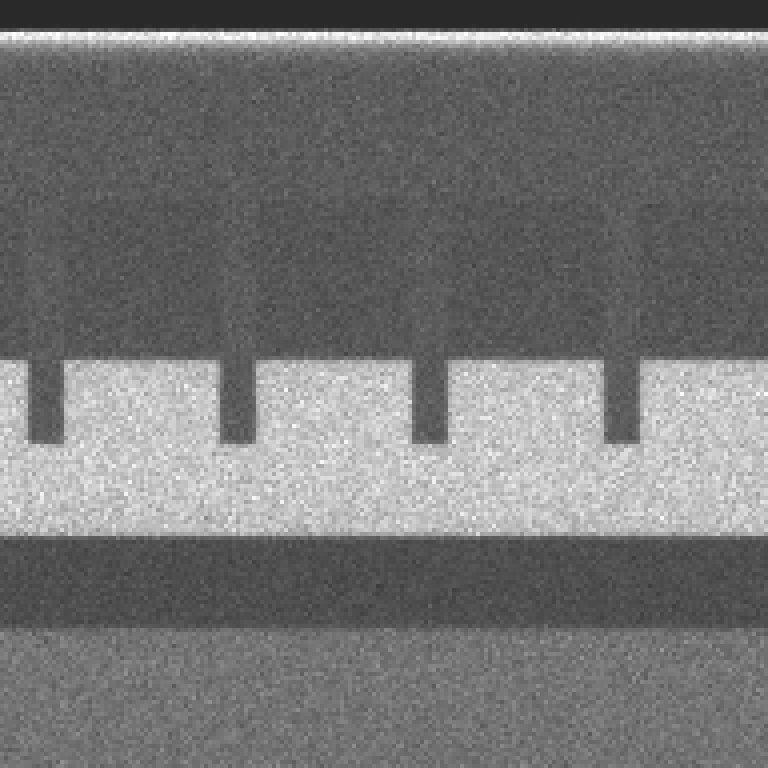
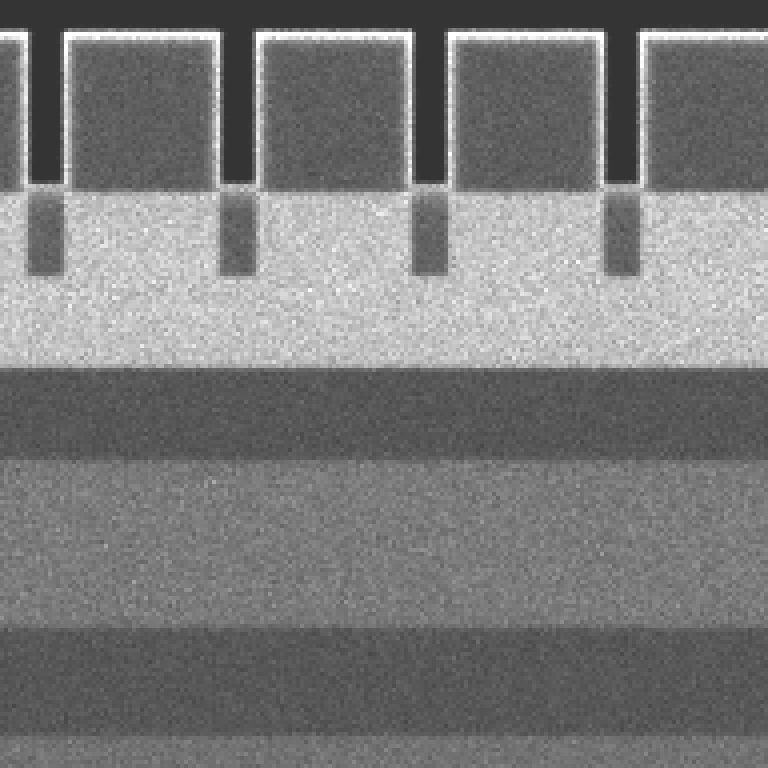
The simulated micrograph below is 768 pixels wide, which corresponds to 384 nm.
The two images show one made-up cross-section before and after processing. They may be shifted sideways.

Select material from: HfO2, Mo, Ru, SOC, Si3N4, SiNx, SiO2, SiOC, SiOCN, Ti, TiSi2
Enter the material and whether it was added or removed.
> SOC / removed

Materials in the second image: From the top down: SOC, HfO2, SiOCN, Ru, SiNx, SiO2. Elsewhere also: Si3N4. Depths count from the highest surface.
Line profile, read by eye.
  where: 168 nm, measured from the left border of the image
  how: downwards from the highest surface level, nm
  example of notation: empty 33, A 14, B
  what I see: Si3N4 80, HfO2 88, SiOCN 46, Ru 84, SiNx 54, SiO2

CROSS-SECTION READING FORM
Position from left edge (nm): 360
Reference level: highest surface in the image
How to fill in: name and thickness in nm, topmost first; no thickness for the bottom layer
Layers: Si3N4 80, HfO2 88, SiOCN 46, Ru 84, SiNx 54, SiO2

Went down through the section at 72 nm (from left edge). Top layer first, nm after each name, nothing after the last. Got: Si3N4 80, HfO2 88, SiOCN 46, Ru 84, SiNx 54, SiO2